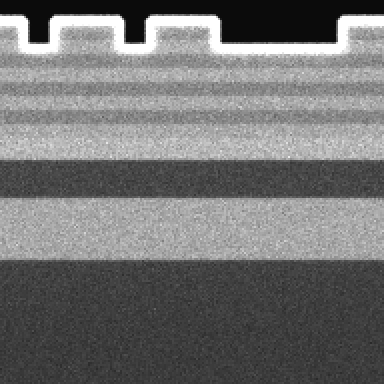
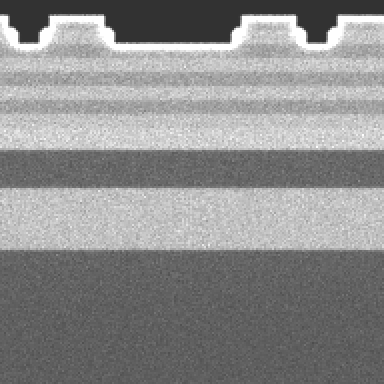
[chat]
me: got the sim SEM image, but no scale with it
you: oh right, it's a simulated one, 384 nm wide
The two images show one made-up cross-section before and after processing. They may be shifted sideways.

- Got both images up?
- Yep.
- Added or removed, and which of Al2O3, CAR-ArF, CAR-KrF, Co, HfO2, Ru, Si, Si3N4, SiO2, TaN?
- removed, Al2O3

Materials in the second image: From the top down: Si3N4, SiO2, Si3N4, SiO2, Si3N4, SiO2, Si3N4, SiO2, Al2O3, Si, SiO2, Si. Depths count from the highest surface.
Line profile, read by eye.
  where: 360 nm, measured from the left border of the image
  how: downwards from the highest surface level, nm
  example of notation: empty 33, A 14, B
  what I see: Si3N4 14, SiO2 14, Si3N4 14, SiO2 14, Si3N4 14, SiO2 14, Si3N4 14, SiO2 14, Al2O3 22, Si 38, SiO2 62, Si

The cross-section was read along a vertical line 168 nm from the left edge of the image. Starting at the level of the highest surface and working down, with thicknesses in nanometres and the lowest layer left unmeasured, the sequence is empty 28, Si3N4 14, SiO2 14, Si3N4 14, SiO2 14, Si3N4 14, SiO2 14, Al2O3 22, Si 38, SiO2 62, Si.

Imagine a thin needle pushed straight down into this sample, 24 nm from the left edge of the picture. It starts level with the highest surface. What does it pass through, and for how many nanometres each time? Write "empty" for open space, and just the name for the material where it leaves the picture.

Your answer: empty 28, Si3N4 14, SiO2 14, Si3N4 14, SiO2 14, Si3N4 14, SiO2 14, Al2O3 22, Si 38, SiO2 62, Si